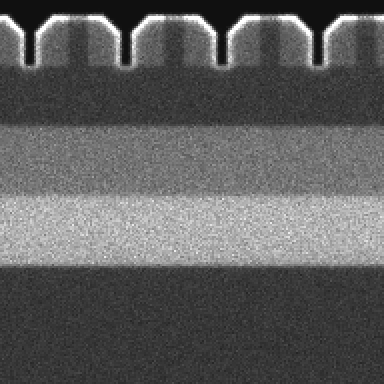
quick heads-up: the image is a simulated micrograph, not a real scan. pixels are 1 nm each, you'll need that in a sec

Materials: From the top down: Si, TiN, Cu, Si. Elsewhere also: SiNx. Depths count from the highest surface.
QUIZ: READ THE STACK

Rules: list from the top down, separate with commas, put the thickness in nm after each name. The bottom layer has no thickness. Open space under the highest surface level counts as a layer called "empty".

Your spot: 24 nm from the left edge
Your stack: empty 50, Si 60, TiN 70, Cu 70, Si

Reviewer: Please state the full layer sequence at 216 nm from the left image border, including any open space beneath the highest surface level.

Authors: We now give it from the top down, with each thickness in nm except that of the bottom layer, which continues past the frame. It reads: empty 50, Si 60, TiN 70, Cu 70, Si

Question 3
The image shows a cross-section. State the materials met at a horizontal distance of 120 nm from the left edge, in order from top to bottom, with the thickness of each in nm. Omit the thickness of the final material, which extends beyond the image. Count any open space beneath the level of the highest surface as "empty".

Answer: empty 50, Si 60, TiN 70, Cu 70, Si